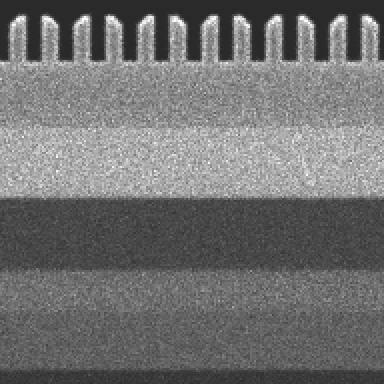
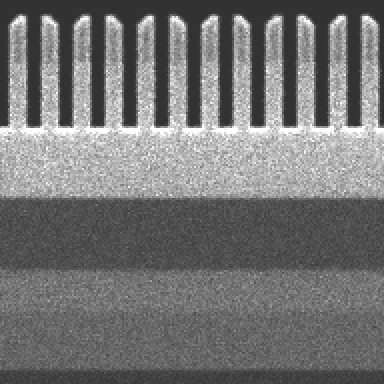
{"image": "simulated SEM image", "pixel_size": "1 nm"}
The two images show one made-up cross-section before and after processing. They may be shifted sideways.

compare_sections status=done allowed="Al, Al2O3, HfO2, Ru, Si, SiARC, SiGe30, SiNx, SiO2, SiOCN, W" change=removed material="W"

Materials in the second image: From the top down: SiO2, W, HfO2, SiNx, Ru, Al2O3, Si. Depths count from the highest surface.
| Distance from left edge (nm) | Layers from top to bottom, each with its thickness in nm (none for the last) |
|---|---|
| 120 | empty 8, SiO2 38, W 66, HfO2 70, SiNx 72, Ru 42, Al2O3 58, Si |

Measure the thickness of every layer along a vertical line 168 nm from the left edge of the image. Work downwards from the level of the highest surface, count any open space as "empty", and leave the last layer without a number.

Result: empty 112, HfO2 70, SiNx 72, Ru 42, Al2O3 58, Si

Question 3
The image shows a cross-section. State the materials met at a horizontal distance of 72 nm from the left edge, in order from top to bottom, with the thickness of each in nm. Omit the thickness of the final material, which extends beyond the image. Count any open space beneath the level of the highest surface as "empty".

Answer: empty 112, HfO2 70, SiNx 72, Ru 42, Al2O3 58, Si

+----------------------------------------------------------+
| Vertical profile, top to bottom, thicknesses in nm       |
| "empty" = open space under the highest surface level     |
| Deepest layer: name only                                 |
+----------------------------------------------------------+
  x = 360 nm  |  empty 112, HfO2 70, SiNx 72, Ru 42, Al2O3 58, Si